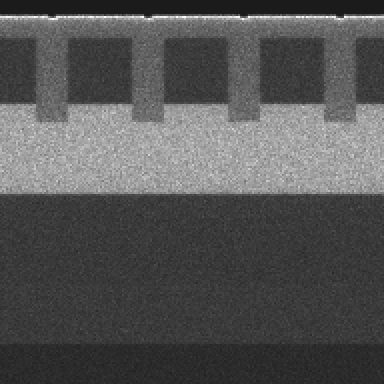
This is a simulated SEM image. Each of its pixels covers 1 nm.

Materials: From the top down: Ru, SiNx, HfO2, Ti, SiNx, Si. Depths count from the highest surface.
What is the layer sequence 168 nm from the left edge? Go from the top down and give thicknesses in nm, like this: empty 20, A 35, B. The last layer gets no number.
Ru 22, SiNx 66, HfO2 90, Ti 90, SiNx 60, Si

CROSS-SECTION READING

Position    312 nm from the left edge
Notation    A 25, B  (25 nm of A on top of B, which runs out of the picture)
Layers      Ru 22, SiNx 66, HfO2 90, Ti 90, SiNx 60, Si